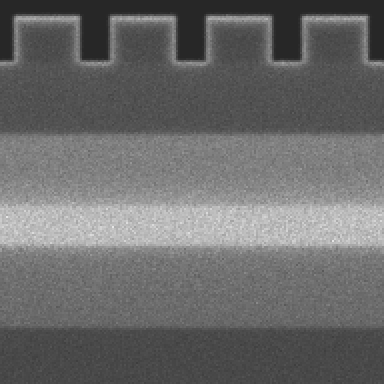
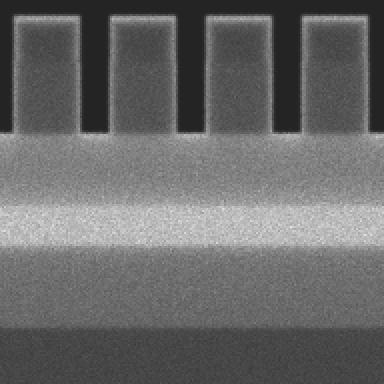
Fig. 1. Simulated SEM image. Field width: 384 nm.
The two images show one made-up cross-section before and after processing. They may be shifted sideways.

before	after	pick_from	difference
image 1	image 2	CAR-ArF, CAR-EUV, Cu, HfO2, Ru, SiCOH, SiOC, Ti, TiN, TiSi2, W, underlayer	TiN removed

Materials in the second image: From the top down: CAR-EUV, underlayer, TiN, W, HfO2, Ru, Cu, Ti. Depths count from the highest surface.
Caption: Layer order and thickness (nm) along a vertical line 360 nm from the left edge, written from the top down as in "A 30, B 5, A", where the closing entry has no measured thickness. CAR-EUV 30, underlayer 16, TiN 72, W 72, HfO2 40, Ru 8, Cu 74, Ti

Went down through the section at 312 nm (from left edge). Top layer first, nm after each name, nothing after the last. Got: CAR-EUV 30, underlayer 16, TiN 72, W 72, HfO2 40, Ru 8, Cu 74, Ti